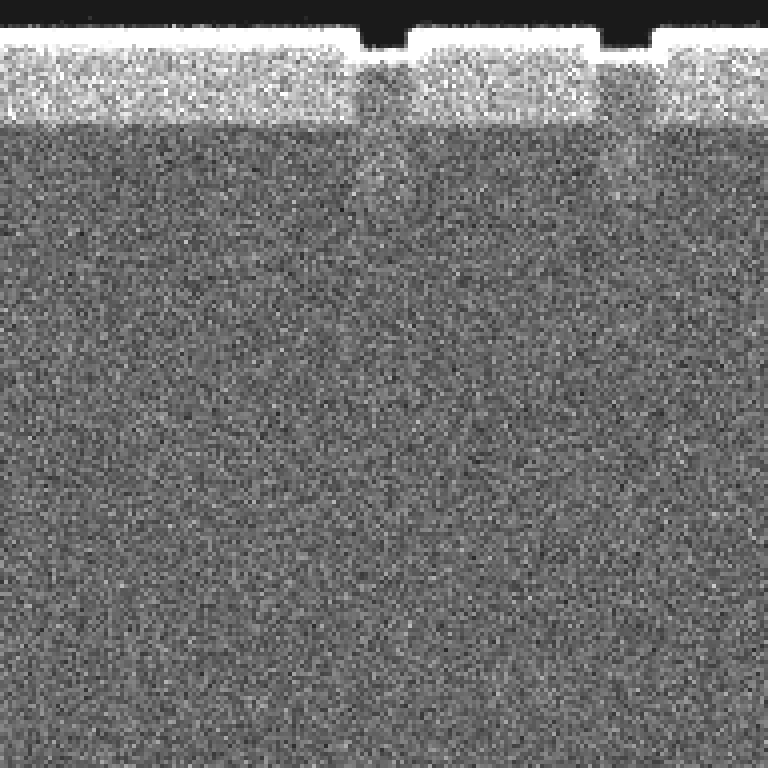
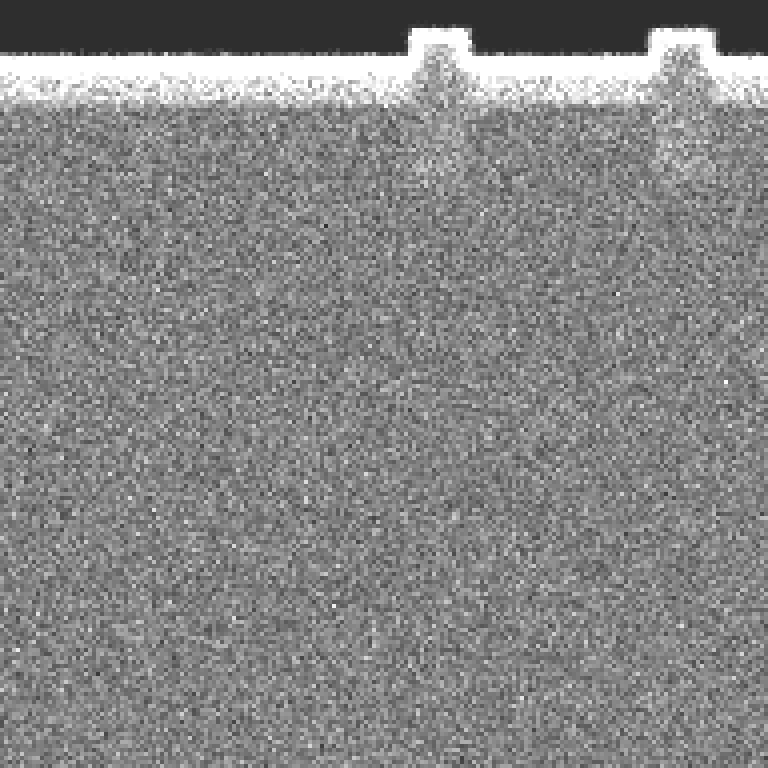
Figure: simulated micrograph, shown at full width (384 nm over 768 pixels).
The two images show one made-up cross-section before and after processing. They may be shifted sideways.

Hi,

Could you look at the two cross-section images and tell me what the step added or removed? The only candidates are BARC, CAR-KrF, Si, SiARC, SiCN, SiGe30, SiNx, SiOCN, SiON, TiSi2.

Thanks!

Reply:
removed SiNx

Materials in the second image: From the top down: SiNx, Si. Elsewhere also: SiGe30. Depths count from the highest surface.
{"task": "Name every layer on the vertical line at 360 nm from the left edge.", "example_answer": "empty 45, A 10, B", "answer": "empty 14, SiNx 22, Si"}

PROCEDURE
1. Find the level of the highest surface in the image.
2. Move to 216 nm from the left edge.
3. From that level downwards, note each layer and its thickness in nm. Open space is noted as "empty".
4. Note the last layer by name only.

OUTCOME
SiGe30 76, Si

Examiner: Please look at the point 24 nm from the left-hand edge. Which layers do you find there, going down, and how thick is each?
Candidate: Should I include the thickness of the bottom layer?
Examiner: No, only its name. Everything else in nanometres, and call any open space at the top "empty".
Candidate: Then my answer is empty 14, SiNx 22, Si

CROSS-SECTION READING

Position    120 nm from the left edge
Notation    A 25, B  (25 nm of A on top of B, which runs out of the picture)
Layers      empty 14, SiNx 22, Si